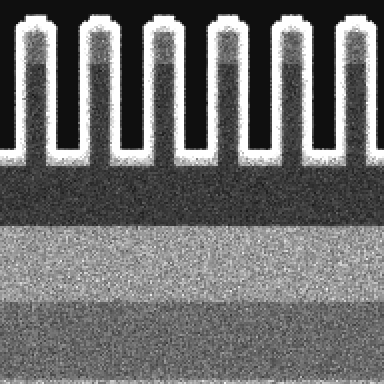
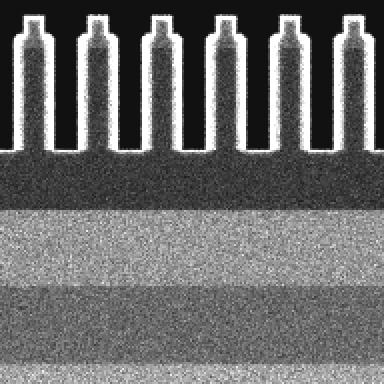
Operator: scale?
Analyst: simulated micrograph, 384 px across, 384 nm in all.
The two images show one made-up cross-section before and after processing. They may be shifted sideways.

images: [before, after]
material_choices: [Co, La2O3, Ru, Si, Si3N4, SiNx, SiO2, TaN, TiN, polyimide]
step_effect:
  removed: SiO2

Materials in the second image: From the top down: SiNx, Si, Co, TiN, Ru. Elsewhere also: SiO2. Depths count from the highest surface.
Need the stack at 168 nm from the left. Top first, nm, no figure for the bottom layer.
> SiNx 32, Si 162, Co 76, TiN 78, Ru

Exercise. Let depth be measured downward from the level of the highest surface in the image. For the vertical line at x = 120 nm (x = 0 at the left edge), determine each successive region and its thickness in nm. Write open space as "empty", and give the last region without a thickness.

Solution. empty 134, Si 60, Co 76, TiN 78, Ru